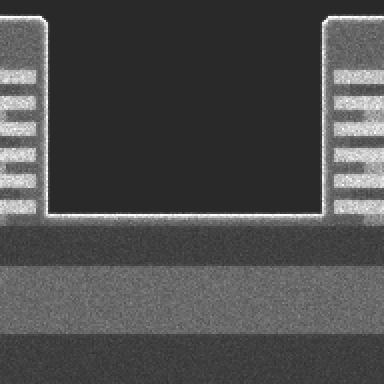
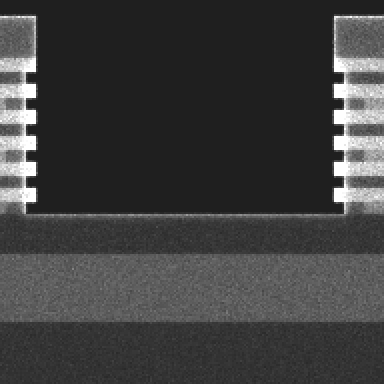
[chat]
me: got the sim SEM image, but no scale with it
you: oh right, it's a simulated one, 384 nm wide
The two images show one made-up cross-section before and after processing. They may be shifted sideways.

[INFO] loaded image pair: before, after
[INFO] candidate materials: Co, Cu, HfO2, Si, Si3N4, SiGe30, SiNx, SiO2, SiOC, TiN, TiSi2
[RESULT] removed Si3N4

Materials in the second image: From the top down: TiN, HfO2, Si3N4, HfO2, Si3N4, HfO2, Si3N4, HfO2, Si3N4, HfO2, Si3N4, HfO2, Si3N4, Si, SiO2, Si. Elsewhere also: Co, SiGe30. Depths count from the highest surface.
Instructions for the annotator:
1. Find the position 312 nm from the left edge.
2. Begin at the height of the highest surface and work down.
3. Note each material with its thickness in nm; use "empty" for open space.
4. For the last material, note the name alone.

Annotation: empty 198, Si 40, SiO2 68, Si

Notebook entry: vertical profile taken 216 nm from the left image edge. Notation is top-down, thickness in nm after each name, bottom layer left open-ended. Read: empty 198, Si 40, SiO2 68, Si